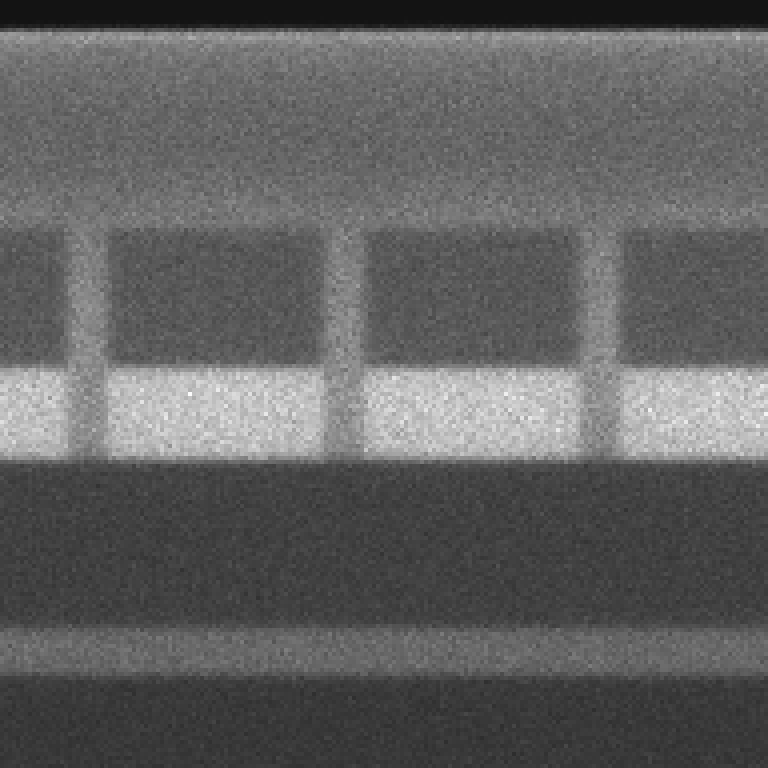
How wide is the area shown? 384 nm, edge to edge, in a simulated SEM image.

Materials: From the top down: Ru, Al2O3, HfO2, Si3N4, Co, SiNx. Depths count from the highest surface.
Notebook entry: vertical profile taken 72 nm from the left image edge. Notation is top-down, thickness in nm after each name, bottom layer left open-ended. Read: Ru 98, Al2O3 70, HfO2 46, Si3N4 84, Co 24, SiNx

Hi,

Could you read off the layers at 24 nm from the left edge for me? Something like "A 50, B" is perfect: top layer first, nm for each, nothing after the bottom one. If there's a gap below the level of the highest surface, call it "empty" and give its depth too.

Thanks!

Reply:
Ru 98, Al2O3 70, HfO2 46, Si3N4 84, Co 24, SiNx